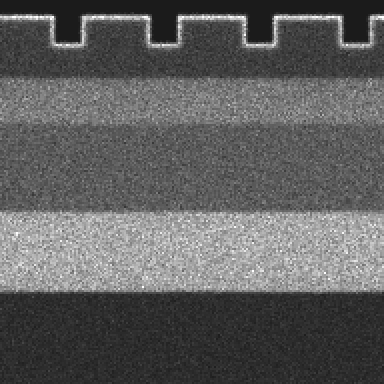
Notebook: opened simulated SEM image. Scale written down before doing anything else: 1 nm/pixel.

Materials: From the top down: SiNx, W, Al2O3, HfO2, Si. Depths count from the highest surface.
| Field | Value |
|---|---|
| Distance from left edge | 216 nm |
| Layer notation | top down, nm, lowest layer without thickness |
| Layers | SiNx 62, W 46, Al2O3 88, HfO2 80, Si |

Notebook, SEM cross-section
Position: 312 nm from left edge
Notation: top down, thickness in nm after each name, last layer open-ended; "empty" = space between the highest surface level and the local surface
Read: SiNx 62, W 46, Al2O3 88, HfO2 80, Si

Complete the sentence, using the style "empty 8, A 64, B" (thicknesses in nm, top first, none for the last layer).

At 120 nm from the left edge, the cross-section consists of SiNx 62, W 46, Al2O3 88, HfO2 80, Si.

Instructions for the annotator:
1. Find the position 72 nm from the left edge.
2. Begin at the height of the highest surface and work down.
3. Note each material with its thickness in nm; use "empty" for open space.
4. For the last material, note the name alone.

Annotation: empty 28, SiNx 34, W 46, Al2O3 88, HfO2 80, Si